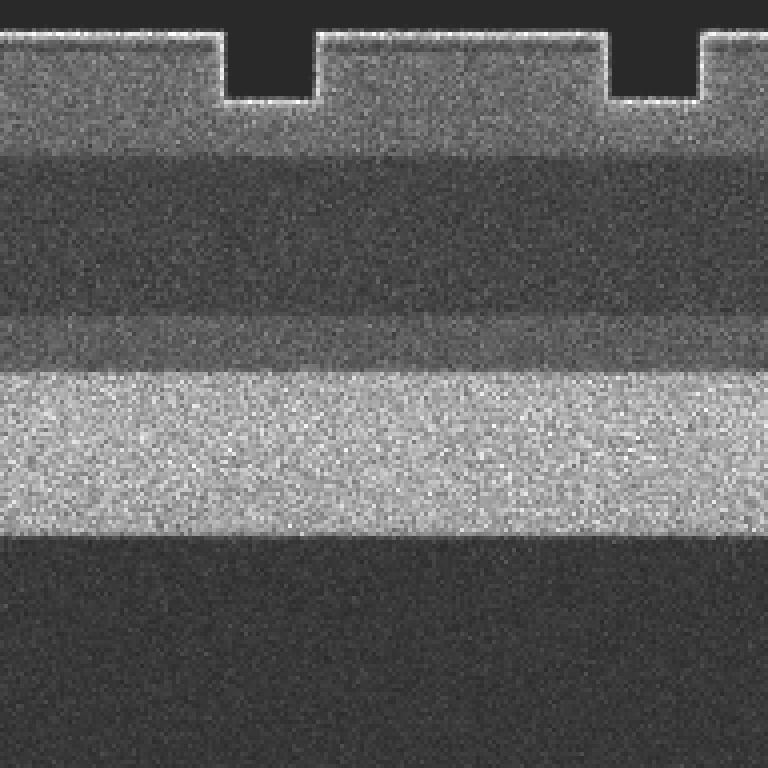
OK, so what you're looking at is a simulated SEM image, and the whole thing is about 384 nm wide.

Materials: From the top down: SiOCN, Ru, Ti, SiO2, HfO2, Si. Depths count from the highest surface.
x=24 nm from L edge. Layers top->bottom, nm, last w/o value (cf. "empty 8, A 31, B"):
SiOCN 10, Ru 52, Ti 80, SiO2 28, HfO2 82, Si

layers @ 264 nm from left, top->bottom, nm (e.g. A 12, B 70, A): SiOCN 10, Ru 52, Ti 80, SiO2 28, HfO2 82, Si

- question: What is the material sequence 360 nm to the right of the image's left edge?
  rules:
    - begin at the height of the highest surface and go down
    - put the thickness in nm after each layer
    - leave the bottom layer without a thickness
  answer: SiOCN 10, Ru 52, Ti 80, SiO2 28, HfO2 82, Si